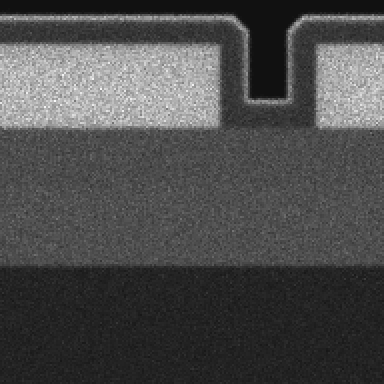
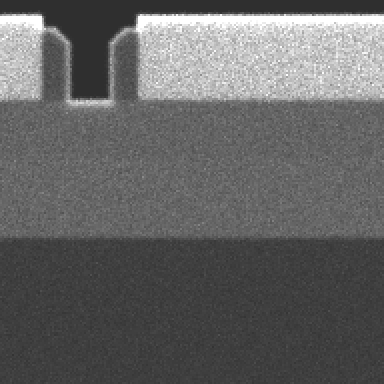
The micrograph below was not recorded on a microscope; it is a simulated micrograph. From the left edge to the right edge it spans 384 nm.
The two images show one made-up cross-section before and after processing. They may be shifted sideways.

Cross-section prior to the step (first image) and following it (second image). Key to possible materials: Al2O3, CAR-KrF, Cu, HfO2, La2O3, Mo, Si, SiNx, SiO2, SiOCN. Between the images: SiNx was removed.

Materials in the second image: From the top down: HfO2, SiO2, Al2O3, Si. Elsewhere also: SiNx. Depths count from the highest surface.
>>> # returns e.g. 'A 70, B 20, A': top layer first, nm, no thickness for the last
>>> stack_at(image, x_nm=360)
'HfO2 84, SiO2 58, Al2O3 80, Si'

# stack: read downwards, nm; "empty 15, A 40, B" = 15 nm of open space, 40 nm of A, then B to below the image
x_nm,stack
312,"HfO2 84, SiO2 58, Al2O3 80, Si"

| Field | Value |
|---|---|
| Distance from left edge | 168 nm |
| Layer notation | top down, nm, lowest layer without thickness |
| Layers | HfO2 84, SiO2 58, Al2O3 80, Si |